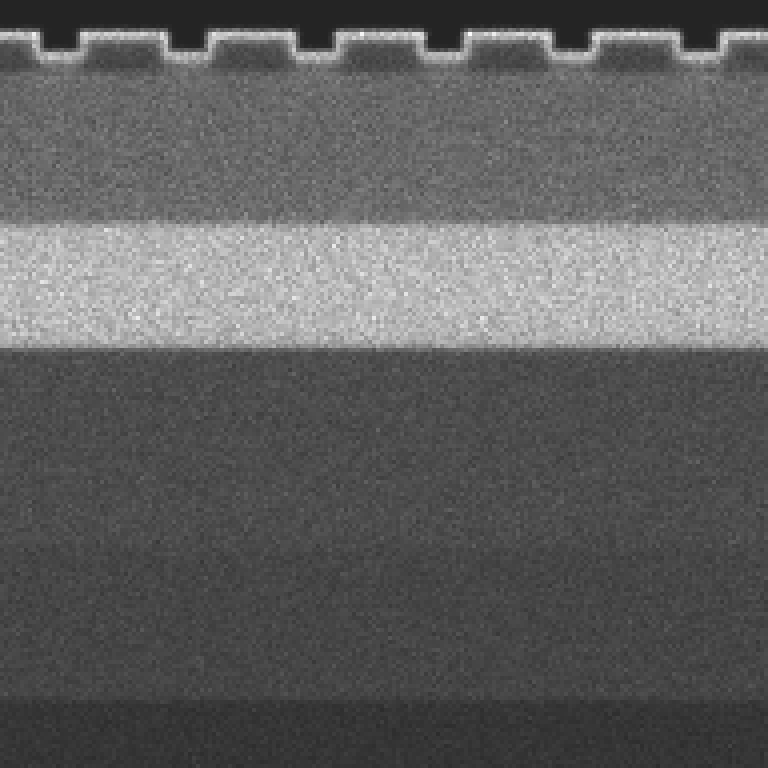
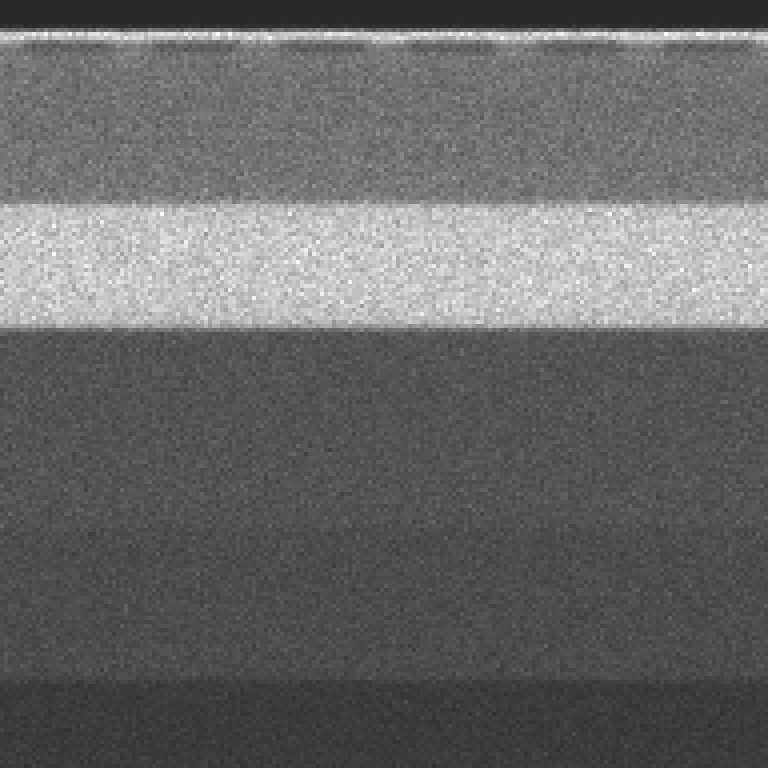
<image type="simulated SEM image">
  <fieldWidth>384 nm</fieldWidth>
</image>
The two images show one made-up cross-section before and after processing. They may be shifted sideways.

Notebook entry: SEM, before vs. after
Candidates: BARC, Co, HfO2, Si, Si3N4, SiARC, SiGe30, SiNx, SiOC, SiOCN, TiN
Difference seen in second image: SiNx removed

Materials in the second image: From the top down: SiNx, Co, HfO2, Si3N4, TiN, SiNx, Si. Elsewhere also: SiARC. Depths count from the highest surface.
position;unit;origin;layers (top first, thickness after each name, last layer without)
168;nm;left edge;SiNx 10, Co 76, HfO2 62, Si3N4 64, TiN 36, SiNx 76, Si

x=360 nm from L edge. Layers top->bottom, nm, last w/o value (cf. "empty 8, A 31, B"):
SiNx 10, Co 76, HfO2 62, Si3N4 64, TiN 36, SiNx 76, Si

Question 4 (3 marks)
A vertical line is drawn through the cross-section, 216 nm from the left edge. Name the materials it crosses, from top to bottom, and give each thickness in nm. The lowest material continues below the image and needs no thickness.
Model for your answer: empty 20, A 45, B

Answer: SiNx 10, Co 76, HfO2 62, Si3N4 64, TiN 36, SiNx 76, Si